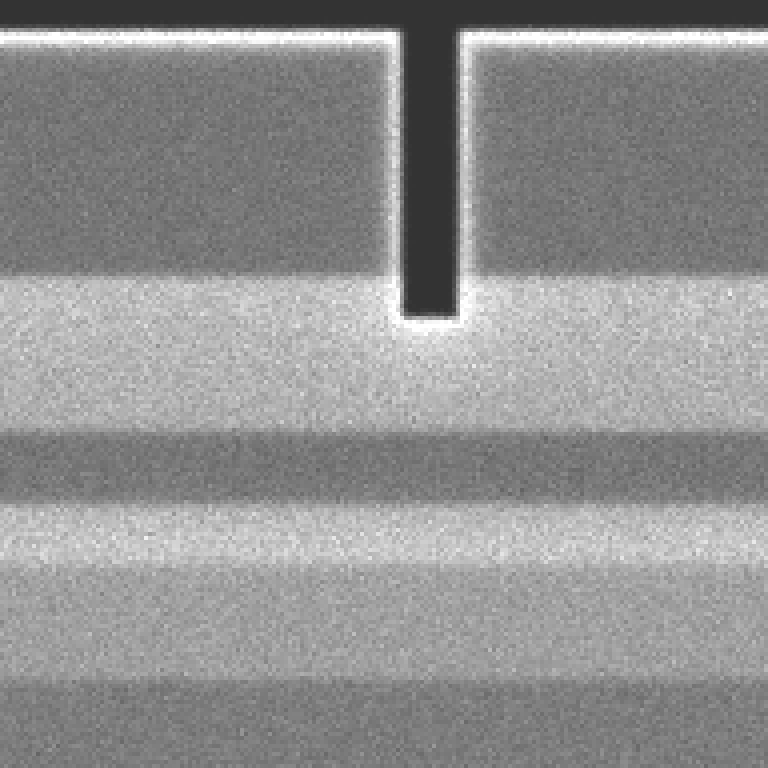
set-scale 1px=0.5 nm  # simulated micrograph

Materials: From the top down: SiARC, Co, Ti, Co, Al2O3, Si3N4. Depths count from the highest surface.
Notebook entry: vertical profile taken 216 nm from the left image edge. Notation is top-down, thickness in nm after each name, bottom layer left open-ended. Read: empty 144, Co 56, Ti 36, Co 30, Al2O3 58, Si3N4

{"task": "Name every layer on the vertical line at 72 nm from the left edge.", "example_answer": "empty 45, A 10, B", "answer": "SiARC 122, Co 78, Ti 36, Co 30, Al2O3 58, Si3N4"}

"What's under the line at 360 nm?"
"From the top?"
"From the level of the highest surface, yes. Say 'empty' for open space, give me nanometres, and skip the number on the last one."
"SiARC 122, Co 78, Ti 36, Co 30, Al2O3 58, Si3N4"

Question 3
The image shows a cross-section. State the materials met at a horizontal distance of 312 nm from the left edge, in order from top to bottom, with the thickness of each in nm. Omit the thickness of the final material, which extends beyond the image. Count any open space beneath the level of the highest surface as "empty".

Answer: SiARC 122, Co 78, Ti 36, Co 30, Al2O3 58, Si3N4